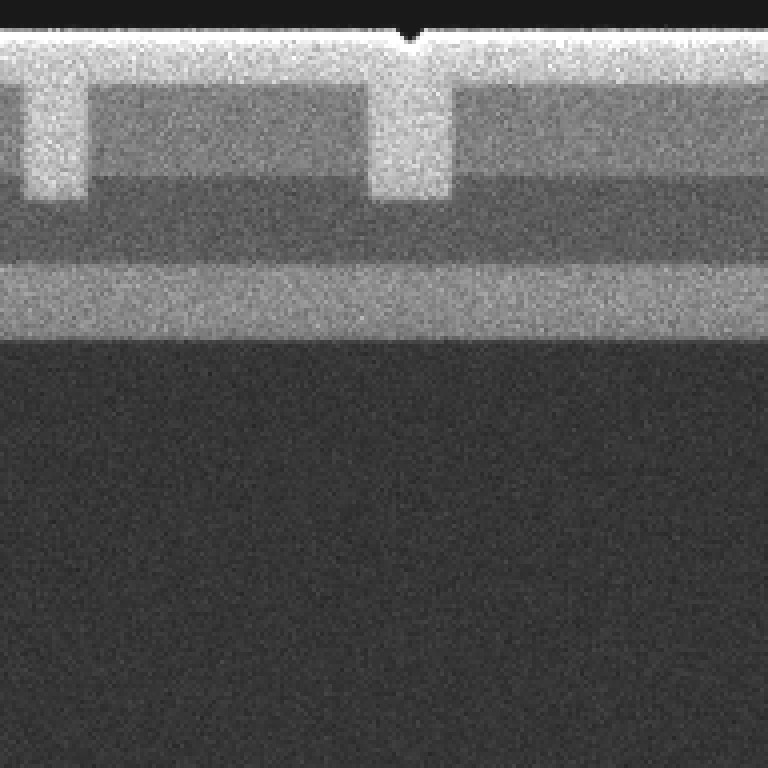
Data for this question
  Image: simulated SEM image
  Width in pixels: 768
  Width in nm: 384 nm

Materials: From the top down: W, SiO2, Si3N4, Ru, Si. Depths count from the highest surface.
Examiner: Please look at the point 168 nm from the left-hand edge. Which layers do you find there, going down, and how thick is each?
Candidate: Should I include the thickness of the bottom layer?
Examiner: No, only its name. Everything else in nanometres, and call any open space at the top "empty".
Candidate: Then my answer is W 26, SiO2 46, Si3N4 44, Ru 38, Si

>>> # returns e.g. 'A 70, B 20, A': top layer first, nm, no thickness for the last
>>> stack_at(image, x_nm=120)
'W 26, SiO2 46, Si3N4 44, Ru 38, Si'